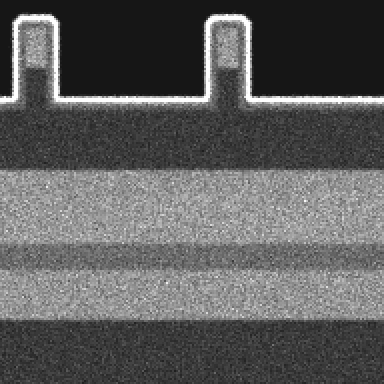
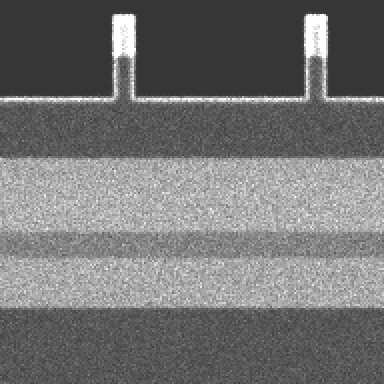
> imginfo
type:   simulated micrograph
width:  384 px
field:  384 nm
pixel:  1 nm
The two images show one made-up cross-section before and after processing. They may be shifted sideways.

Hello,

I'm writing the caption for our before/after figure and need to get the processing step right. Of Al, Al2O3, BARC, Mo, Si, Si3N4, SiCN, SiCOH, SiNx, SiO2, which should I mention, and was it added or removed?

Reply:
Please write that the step removed SiNx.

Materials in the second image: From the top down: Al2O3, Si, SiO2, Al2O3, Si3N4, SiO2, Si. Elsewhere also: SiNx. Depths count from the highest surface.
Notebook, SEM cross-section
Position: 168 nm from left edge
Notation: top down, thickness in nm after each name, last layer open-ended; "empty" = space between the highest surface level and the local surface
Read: empty 82, Si 60, SiO2 24, Al2O3 50, Si3N4 26, SiO2 50, Si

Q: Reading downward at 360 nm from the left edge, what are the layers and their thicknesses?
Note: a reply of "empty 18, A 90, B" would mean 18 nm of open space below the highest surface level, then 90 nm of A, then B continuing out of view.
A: empty 82, Si 60, SiO2 24, Al2O3 50, Si3N4 26, SiO2 50, Si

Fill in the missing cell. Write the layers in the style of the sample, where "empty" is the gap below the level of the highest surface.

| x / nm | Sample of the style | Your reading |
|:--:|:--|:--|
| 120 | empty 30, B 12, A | Al2O3 40, Si 102, SiO2 24, Al2O3 50, Si3N4 26, SiO2 50, Si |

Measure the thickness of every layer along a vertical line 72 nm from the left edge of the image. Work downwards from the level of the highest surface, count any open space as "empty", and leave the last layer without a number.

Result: empty 82, Si 60, SiO2 24, Al2O3 50, Si3N4 26, SiO2 50, Si